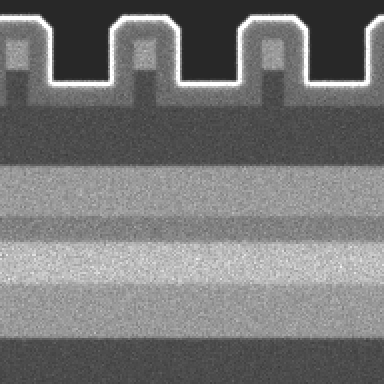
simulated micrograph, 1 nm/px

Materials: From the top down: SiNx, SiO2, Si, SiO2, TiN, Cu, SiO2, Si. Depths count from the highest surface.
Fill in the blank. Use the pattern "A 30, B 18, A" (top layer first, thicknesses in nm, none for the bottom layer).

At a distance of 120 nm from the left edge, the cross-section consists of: empty 2, SiNx 88, Si 60, SiO2 50, TiN 26, Cu 42, SiO2 54, Si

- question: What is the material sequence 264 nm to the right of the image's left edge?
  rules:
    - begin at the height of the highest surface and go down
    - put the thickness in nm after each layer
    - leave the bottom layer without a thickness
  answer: SiNx 24, SiO2 30, Si 96, SiO2 50, TiN 26, Cu 42, SiO2 54, Si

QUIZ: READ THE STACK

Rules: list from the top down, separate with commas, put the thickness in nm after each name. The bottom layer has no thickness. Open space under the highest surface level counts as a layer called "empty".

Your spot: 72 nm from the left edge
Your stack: empty 66, SiNx 24, Si 60, SiO2 50, TiN 26, Cu 42, SiO2 54, Si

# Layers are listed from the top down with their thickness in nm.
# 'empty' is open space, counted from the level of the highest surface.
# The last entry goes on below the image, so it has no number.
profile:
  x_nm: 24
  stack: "SiNx 24, SiO2 30, Si 96, SiO2 50, TiN 26, Cu 42, SiO2 54, Si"